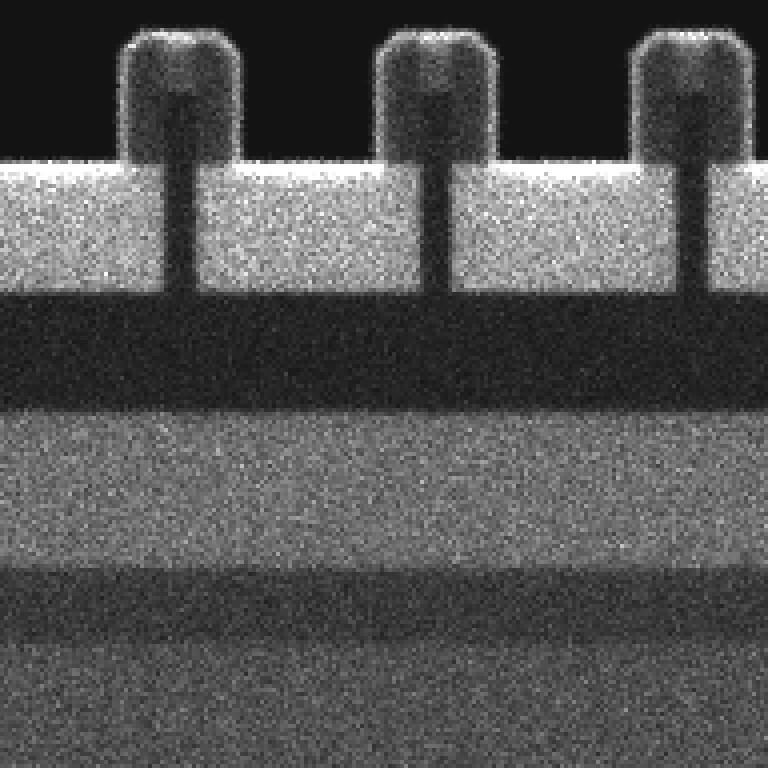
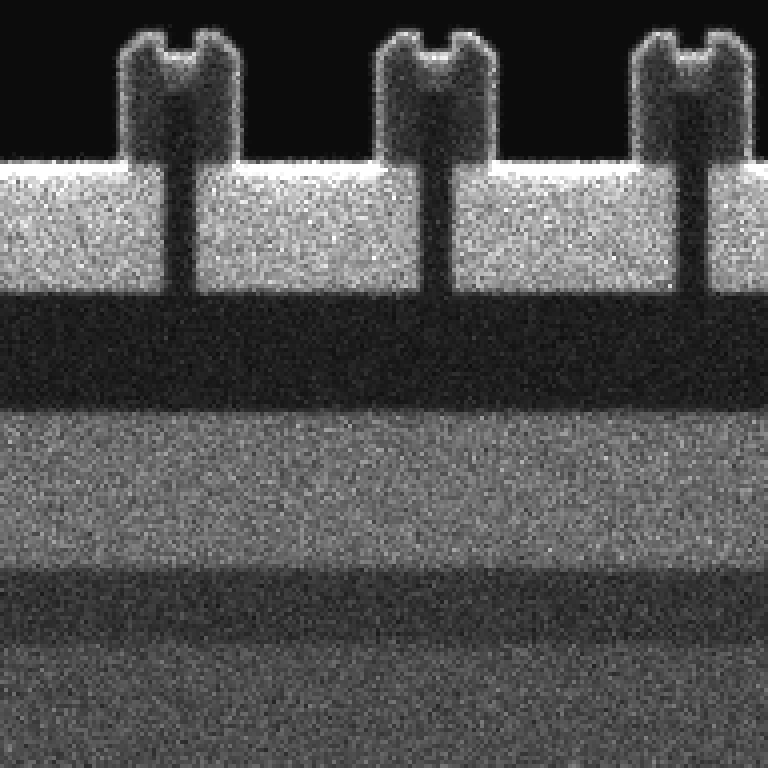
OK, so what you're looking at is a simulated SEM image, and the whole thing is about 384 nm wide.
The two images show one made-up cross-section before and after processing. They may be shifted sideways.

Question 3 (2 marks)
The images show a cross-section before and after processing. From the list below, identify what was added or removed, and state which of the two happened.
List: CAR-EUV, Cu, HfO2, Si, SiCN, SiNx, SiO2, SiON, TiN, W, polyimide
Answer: SiO2 was removed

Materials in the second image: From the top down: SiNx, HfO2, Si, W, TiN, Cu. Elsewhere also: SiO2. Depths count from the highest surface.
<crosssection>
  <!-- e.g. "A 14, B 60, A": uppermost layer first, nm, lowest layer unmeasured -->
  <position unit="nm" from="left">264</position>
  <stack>empty 66, HfO2 64, Si 60, W 78, TiN 38, Cu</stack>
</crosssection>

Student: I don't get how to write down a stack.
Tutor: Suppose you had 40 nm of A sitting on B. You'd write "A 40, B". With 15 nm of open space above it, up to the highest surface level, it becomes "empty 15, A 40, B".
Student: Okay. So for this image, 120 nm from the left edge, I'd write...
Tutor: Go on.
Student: empty 66, HfO2 64, Si 60, W 78, TiN 38, Cu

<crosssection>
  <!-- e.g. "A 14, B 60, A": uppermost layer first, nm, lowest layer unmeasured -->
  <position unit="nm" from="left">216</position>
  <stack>empty 10, SiO2 20, Si 160, W 78, TiN 38, Cu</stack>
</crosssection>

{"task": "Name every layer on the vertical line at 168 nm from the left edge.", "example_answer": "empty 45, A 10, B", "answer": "empty 66, HfO2 64, Si 60, W 78, TiN 38, Cu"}